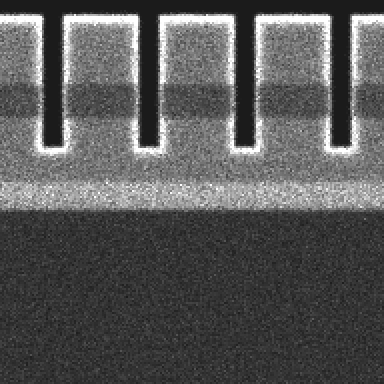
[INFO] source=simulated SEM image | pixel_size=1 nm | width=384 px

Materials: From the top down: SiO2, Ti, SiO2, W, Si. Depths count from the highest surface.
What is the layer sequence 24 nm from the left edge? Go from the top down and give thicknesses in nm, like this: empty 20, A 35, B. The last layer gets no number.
SiO2 68, Ti 34, SiO2 64, W 28, Si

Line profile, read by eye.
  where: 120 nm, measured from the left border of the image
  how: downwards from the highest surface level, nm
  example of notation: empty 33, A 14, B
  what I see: SiO2 68, Ti 34, SiO2 64, W 28, Si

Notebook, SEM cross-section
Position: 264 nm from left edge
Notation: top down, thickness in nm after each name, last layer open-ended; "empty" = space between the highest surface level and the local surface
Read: SiO2 68, Ti 34, SiO2 64, W 28, Si